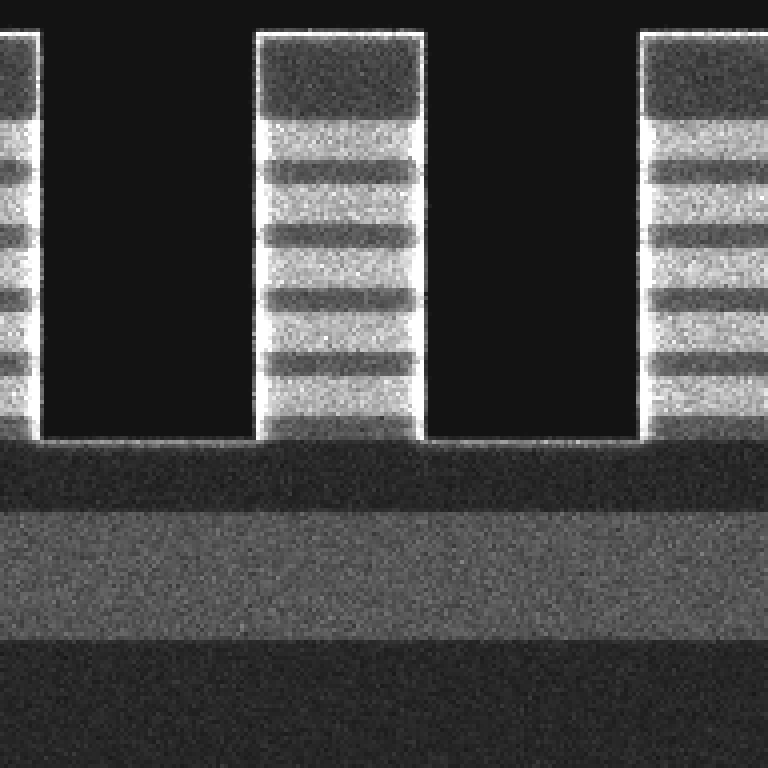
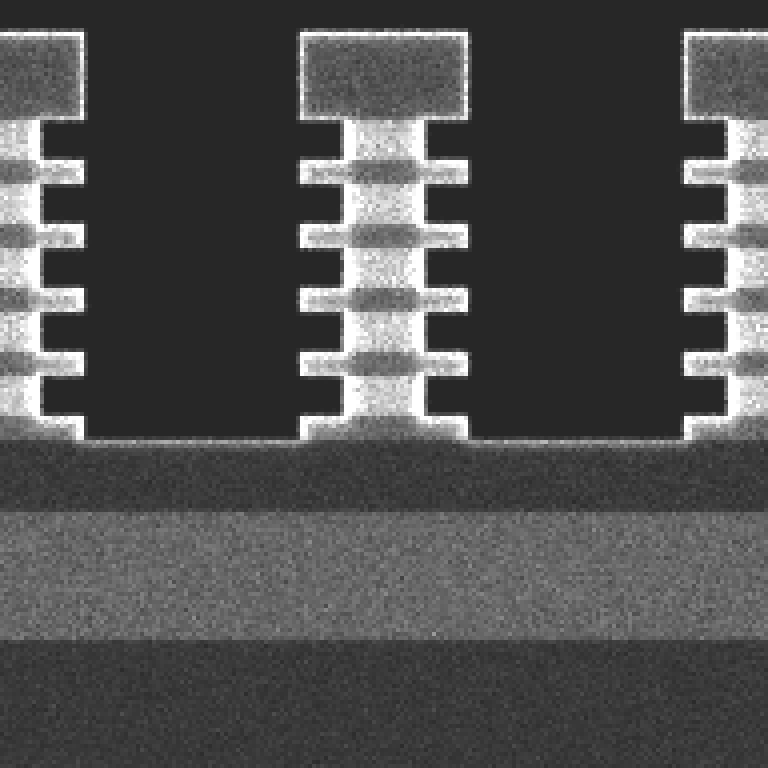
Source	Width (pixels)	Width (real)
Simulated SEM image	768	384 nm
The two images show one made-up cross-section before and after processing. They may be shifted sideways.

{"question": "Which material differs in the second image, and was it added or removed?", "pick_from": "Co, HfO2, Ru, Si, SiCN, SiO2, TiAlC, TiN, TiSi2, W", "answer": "HfO2, removed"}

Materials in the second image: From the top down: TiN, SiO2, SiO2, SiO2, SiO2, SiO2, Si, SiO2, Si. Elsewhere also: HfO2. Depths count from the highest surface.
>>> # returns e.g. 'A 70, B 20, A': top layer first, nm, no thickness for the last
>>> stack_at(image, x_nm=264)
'empty 204, Si 36, SiO2 64, Si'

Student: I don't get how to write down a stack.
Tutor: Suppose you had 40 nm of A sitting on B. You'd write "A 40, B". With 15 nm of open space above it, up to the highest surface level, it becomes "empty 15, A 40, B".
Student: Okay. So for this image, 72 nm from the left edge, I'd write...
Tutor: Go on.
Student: empty 204, Si 36, SiO2 64, Si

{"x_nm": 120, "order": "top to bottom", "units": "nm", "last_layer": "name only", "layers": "empty 204, Si 36, SiO2 64, Si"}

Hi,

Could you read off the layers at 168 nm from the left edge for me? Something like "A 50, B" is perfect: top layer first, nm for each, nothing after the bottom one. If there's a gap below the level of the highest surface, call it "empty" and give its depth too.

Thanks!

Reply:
TiN 44, empty 20, SiO2 12, empty 20, SiO2 12, empty 20, SiO2 12, empty 20, SiO2 12, empty 20, SiO2 12, Si 36, SiO2 64, Si